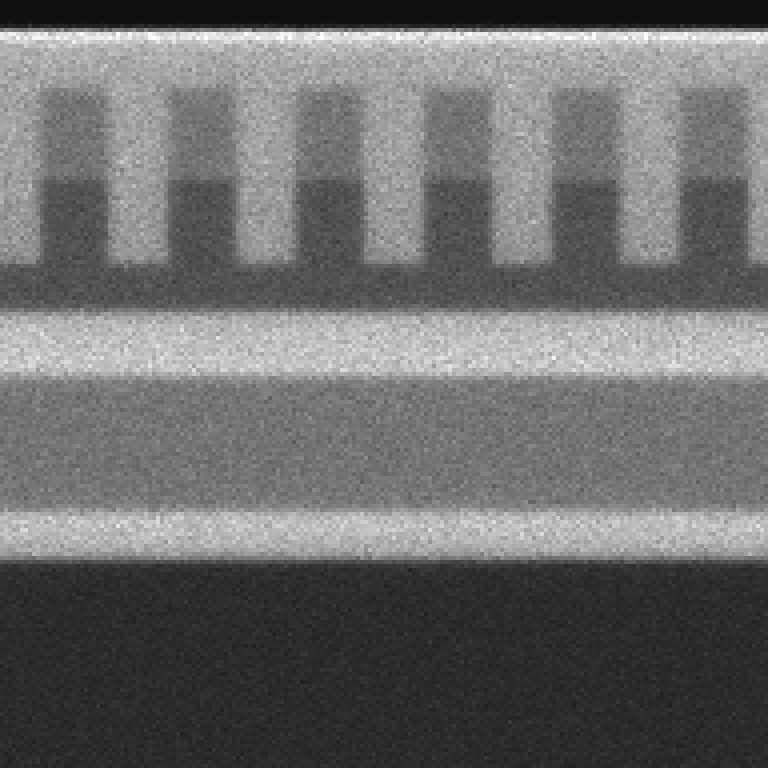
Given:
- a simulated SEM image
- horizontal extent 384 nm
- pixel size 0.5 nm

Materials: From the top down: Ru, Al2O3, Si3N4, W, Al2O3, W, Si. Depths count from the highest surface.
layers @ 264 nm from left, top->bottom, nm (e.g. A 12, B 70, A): Ru 116, Si3N4 24, W 32, Al2O3 68, W 24, Si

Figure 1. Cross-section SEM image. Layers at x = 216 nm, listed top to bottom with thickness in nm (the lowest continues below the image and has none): Ru 28, Al2O3 46, Si3N4 66, W 32, Al2O3 68, W 24, Si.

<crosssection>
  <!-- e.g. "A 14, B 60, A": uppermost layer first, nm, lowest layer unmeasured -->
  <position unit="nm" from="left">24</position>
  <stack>Ru 28, Al2O3 46, Si3N4 66, W 32, Al2O3 68, W 24, Si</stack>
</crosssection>